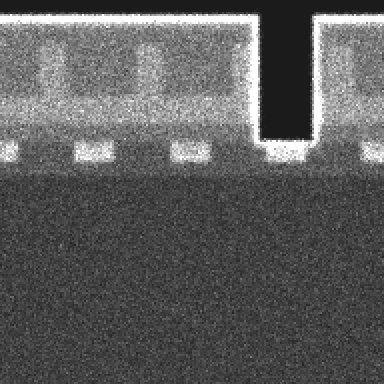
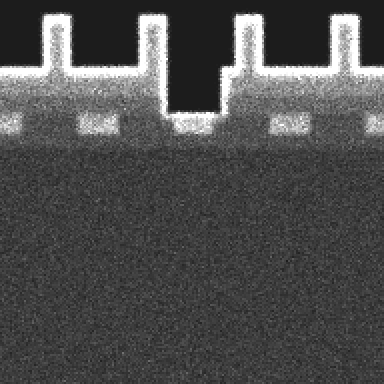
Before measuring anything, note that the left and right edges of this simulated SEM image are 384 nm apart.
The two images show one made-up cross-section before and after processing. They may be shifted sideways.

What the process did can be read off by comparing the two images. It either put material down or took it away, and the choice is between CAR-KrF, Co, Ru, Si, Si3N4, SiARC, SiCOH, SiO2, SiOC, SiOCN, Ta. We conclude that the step removed SiARC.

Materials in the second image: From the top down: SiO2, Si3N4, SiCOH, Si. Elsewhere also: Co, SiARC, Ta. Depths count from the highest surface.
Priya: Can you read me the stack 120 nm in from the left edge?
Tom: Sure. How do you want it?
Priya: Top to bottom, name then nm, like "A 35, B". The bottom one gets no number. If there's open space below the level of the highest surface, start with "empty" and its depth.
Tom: empty 52, SiO2 28, Si3N4 18, SiCOH 34, Si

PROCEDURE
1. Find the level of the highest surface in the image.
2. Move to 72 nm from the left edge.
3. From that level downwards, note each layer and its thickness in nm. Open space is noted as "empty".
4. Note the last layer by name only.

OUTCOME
empty 52, SiO2 28, Si3N4 18, SiCOH 34, Si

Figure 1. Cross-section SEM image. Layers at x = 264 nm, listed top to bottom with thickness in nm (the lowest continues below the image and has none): empty 52, SiO2 28, Si3N4 18, SiCOH 34, Si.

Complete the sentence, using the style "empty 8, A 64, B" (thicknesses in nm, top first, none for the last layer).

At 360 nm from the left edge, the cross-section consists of empty 52, SiO2 28, Si3N4 18, SiCOH 34, Si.